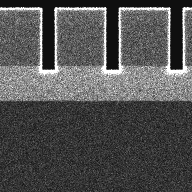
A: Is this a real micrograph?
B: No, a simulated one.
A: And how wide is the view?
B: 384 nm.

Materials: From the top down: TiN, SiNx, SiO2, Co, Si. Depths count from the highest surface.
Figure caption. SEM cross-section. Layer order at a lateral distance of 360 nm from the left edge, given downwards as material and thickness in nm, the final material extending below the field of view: empty 124, SiO2 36, Co 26, Si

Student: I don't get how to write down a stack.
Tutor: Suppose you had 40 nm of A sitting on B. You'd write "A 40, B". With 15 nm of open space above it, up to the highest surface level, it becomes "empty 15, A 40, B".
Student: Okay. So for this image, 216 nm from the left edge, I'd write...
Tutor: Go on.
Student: empty 124, SiO2 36, Co 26, Si